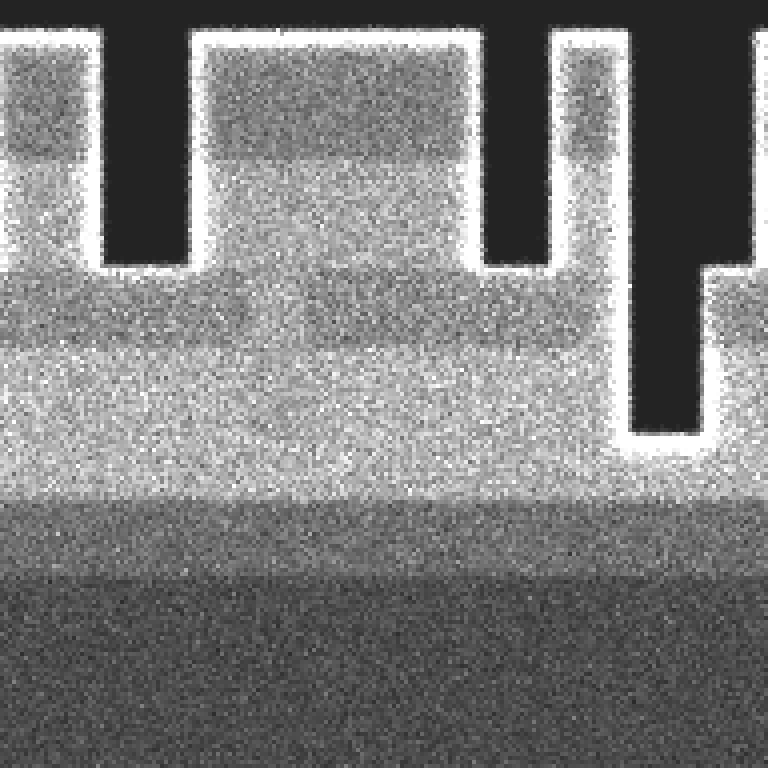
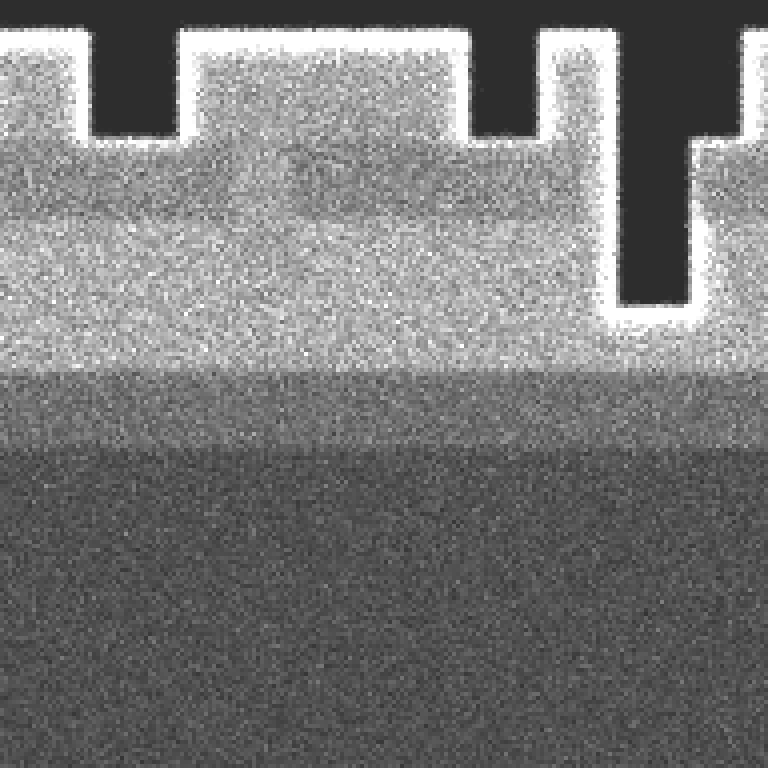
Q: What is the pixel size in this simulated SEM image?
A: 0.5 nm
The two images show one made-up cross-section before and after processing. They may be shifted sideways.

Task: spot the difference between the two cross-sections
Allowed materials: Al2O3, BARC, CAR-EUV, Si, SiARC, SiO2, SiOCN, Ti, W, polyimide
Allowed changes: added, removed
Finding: removed SiARC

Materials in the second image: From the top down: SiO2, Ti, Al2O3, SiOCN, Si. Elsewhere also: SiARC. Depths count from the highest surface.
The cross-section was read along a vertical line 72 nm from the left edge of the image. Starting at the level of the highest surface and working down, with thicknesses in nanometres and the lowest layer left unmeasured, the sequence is empty 54, Ti 40, Al2O3 76, SiOCN 38, Si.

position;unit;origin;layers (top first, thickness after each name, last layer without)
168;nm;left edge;SiO2 54, Ti 40, Al2O3 76, SiOCN 38, Si